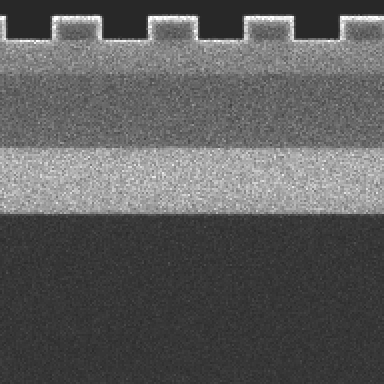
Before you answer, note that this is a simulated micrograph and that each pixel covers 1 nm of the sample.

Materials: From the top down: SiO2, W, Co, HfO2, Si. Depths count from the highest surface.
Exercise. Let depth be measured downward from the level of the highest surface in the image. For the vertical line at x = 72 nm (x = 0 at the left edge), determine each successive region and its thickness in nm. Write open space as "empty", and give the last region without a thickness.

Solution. SiO2 24, W 34, Co 74, HfO2 66, Si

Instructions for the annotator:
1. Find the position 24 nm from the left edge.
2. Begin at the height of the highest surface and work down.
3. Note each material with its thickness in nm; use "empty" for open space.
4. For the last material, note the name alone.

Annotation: empty 24, W 34, Co 74, HfO2 66, Si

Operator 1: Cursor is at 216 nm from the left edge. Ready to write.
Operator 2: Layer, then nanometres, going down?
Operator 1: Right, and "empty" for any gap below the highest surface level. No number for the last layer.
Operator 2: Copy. empty 24, W 34, Co 74, HfO2 66, Si